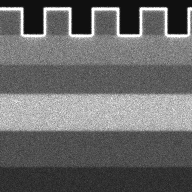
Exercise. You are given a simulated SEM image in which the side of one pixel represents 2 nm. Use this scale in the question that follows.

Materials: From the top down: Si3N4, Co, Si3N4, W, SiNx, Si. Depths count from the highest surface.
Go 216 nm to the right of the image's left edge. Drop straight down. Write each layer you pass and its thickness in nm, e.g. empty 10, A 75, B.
Si3N4 54, Co 60, Si3N4 58, W 74, SiNx 72, Si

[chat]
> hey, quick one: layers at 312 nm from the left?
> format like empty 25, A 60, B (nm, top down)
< Si3N4 54, Co 60, Si3N4 58, W 74, SiNx 72, Si